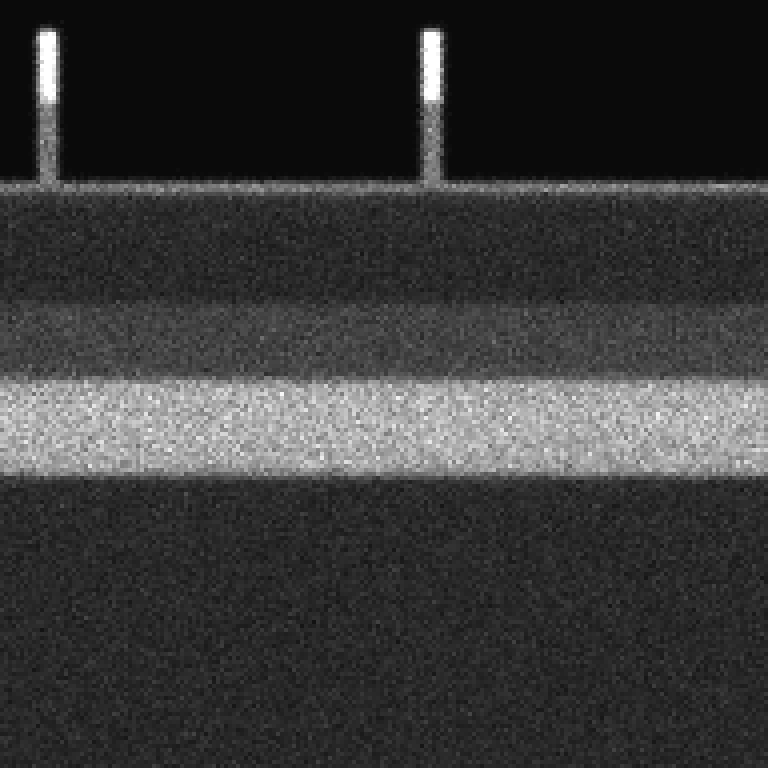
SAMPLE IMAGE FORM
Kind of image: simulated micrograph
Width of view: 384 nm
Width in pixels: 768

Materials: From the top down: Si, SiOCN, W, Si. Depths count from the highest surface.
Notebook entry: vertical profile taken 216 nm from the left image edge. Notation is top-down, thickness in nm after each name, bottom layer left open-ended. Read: Si 136, SiOCN 38, W 48, Si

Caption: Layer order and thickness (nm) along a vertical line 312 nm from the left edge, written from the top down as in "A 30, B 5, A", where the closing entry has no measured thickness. empty 76, Si 60, SiOCN 38, W 48, Si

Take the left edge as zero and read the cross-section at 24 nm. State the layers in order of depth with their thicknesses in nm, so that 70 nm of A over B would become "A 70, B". Si 136, SiOCN 38, W 48, Si